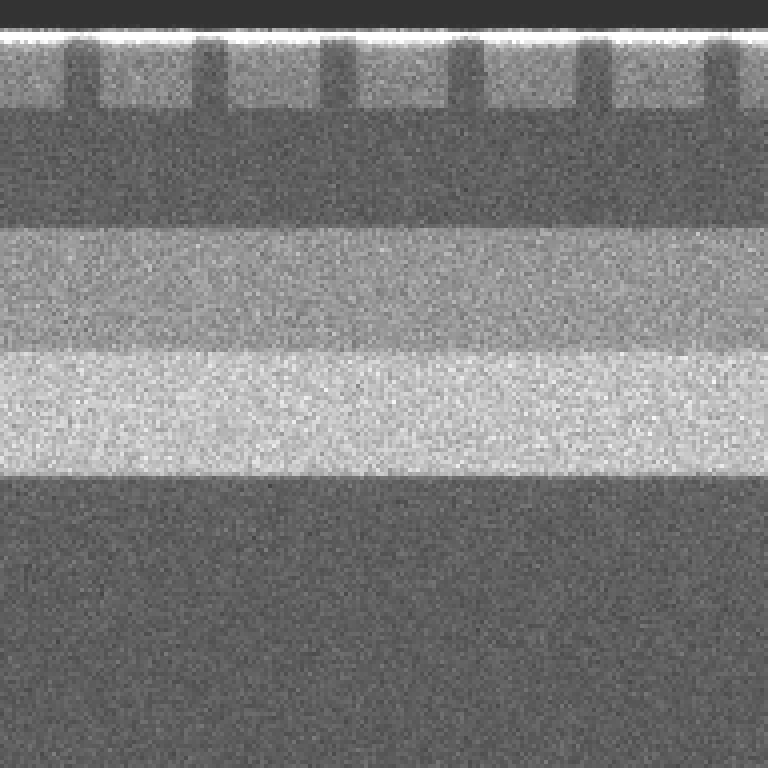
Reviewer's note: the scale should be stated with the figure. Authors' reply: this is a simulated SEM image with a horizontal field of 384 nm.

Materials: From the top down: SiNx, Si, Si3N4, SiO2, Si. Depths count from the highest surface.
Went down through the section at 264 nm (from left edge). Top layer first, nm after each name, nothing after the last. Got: SiNx 38, Si 60, Si3N4 62, SiO2 62, Si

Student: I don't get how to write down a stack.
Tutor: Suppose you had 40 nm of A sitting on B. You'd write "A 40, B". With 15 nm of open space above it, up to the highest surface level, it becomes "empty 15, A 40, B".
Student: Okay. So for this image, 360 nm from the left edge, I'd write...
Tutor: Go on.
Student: Si 98, Si3N4 62, SiO2 62, Si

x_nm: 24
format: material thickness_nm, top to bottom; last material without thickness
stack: SiNx 38, Si 60, Si3N4 62, SiO2 62, Si